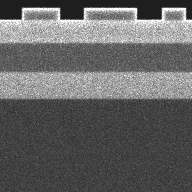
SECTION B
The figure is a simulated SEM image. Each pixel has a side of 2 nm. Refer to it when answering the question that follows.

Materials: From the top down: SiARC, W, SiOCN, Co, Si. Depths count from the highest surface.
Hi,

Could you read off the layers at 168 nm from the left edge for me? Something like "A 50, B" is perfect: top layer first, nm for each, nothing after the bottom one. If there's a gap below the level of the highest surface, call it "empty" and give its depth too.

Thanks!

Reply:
SiARC 24, W 46, SiOCN 58, Co 54, Si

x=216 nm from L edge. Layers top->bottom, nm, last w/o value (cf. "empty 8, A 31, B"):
SiARC 24, W 46, SiOCN 58, Co 54, Si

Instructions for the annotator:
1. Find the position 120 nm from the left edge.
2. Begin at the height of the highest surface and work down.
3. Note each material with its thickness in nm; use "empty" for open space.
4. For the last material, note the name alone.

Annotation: empty 24, W 46, SiOCN 58, Co 54, Si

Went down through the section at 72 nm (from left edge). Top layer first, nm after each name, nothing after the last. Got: SiARC 24, W 46, SiOCN 58, Co 54, Si